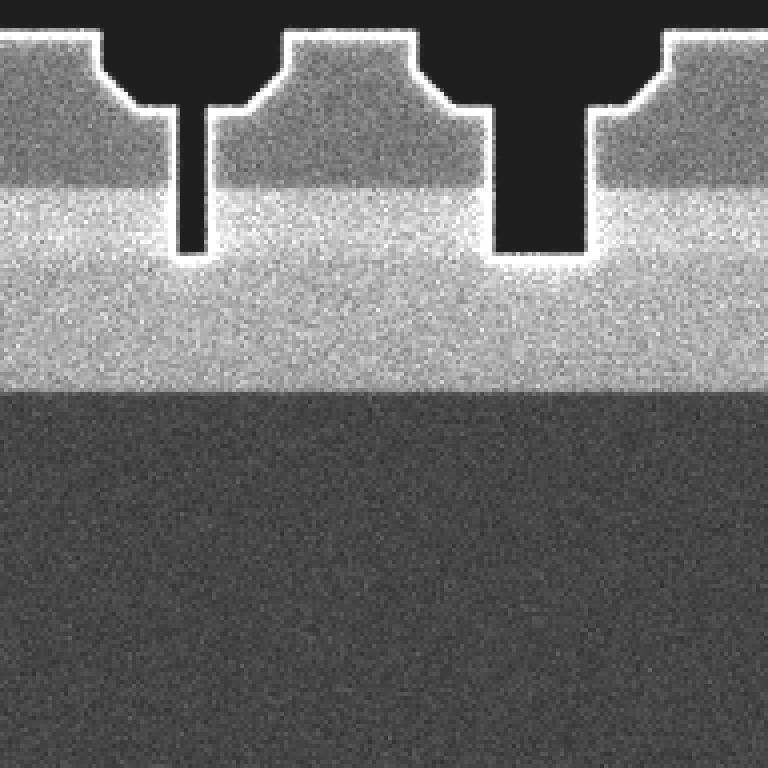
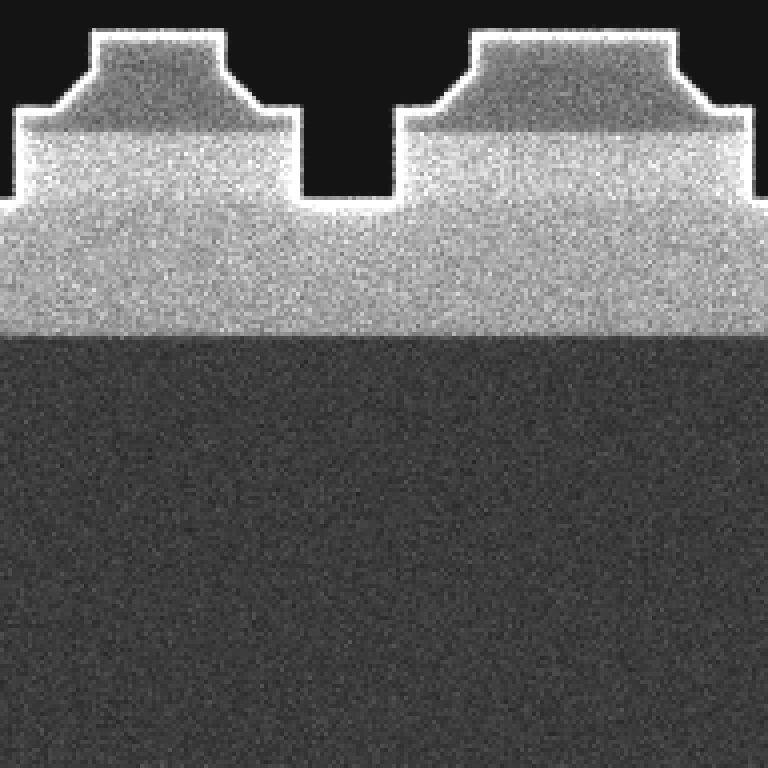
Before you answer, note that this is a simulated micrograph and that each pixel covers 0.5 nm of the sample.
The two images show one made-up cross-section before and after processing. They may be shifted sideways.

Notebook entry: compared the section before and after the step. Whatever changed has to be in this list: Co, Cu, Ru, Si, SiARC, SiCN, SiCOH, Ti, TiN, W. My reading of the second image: TiN removed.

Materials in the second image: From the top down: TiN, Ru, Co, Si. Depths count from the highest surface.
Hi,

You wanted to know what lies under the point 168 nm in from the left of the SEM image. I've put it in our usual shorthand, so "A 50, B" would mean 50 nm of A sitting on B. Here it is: empty 84, Co 68, Si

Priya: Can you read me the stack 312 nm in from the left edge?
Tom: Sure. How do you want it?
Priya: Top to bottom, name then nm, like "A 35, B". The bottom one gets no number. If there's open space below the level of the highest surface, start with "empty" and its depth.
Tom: TiN 50, Ru 34, Co 68, Si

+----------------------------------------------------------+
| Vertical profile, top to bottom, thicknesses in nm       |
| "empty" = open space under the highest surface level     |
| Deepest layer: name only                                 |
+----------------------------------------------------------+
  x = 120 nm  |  empty 28, TiN 22, Ru 34, Co 68, Si